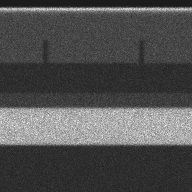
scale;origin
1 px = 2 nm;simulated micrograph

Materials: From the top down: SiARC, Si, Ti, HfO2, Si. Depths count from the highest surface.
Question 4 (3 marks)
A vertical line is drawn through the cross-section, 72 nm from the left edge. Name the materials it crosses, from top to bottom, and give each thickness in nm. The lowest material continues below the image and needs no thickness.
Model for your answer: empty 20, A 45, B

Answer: SiARC 110, Si 60, Ti 30, HfO2 74, Si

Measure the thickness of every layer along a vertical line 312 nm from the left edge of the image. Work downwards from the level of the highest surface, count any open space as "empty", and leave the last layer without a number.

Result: SiARC 110, Si 60, Ti 30, HfO2 74, Si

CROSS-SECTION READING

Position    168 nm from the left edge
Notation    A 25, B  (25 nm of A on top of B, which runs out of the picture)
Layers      SiARC 110, Si 60, Ti 30, HfO2 74, Si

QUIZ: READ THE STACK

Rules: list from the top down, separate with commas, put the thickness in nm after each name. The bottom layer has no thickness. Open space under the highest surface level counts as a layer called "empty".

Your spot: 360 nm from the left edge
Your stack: SiARC 110, Si 60, Ti 30, HfO2 74, Si